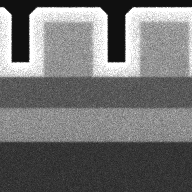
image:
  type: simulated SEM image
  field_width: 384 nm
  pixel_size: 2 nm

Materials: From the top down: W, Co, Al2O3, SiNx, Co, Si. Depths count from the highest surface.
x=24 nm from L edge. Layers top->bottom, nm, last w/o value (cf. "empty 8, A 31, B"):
empty 110, W 28, SiNx 62, Co 68, Si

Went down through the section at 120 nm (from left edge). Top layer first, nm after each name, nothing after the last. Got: W 28, Co 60, Al2O3 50, SiNx 62, Co 68, Si